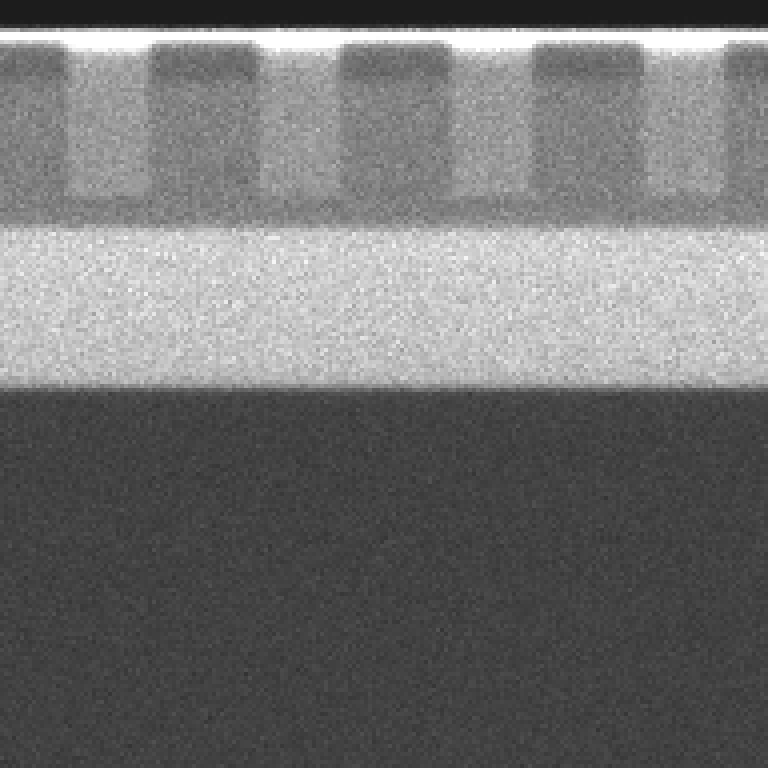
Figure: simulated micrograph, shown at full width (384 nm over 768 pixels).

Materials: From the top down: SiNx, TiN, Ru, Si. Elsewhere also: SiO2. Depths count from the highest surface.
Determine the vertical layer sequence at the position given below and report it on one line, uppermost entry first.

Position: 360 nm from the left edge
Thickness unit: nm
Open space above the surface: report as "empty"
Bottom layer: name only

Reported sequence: SiO2 82, TiN 16, Ru 80, Si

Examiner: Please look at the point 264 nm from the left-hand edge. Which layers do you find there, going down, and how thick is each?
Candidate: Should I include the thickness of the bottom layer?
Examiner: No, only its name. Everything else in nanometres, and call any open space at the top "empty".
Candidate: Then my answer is SiO2 82, TiN 16, Ru 80, Si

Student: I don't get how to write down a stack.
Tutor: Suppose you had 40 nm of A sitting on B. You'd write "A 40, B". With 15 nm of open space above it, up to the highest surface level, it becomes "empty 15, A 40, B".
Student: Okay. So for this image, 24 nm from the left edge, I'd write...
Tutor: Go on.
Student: SiNx 24, TiN 74, Ru 80, Si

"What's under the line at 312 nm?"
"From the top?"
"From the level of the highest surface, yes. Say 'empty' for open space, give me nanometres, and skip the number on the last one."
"SiNx 24, TiN 74, Ru 80, Si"